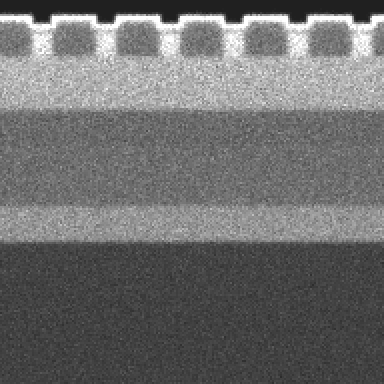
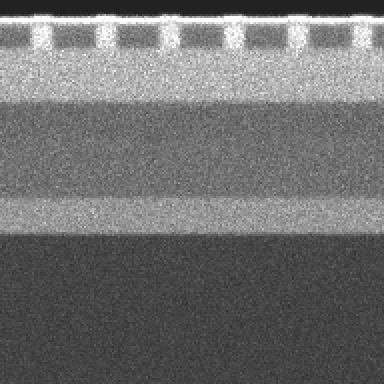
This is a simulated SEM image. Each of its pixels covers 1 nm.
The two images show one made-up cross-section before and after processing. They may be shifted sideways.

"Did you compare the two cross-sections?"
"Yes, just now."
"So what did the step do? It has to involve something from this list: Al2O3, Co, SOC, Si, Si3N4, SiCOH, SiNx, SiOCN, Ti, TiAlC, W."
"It removed Si3N4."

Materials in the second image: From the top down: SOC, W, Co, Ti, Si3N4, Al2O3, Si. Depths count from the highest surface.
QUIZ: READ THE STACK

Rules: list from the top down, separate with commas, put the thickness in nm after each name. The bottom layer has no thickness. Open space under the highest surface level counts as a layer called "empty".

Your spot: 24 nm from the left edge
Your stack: empty 2, Si3N4 30, Co 54, Ti 36, Si3N4 60, Al2O3 36, Si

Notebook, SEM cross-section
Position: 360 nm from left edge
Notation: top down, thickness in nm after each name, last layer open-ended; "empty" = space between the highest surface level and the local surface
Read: SOC 10, W 22, Co 54, Ti 36, Si3N4 60, Al2O3 36, Si